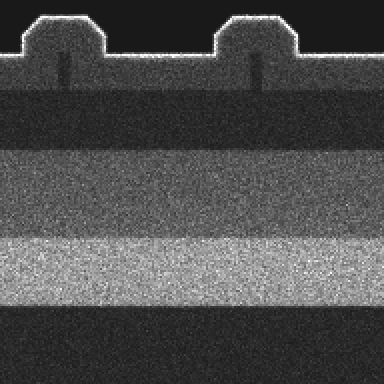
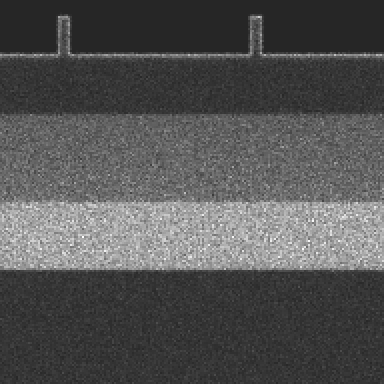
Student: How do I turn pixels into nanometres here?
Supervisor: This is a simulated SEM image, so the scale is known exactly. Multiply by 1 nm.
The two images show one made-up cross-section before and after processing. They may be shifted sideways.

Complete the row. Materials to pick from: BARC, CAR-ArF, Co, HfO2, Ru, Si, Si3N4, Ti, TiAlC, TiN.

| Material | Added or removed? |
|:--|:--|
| Si3N4 | removed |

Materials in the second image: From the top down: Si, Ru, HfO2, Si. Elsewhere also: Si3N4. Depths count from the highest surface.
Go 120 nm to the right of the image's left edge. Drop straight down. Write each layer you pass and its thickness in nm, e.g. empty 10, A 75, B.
empty 38, Si 60, Ru 88, HfO2 68, Si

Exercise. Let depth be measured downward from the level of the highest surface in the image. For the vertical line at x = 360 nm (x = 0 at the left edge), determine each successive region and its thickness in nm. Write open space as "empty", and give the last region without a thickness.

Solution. empty 38, Si 60, Ru 88, HfO2 68, Si